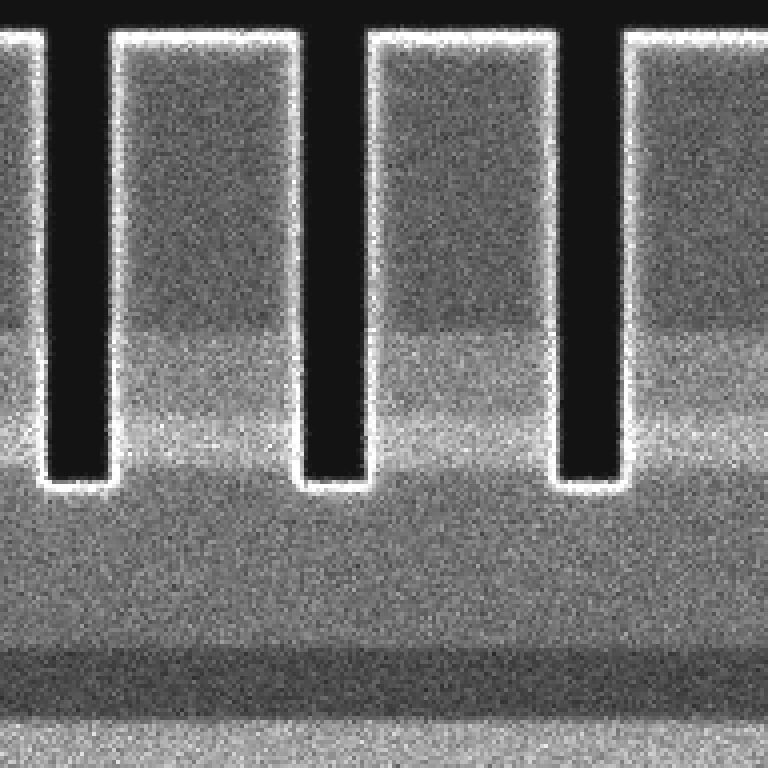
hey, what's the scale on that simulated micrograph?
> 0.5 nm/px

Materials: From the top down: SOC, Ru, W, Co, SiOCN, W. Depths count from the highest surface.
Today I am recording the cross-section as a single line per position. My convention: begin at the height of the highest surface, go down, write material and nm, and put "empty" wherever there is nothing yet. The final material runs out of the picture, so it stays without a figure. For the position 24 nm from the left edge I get empty 226, Co 82, SiOCN 36, W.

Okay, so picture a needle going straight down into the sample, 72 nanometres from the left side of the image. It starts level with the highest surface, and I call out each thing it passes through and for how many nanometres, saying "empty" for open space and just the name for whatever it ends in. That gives SOC 150, Ru 42, W 26, Co 90, SiOCN 36, W